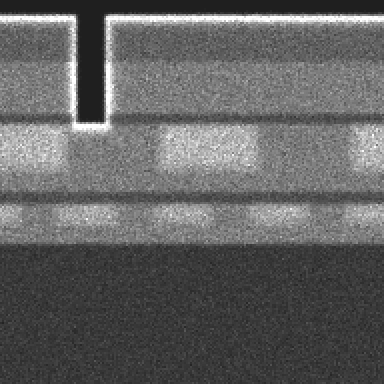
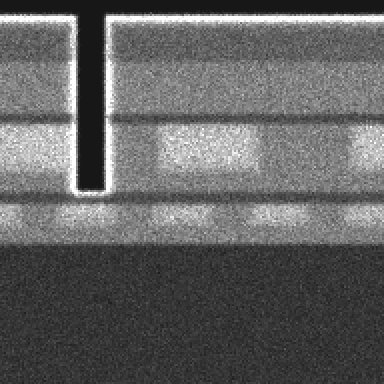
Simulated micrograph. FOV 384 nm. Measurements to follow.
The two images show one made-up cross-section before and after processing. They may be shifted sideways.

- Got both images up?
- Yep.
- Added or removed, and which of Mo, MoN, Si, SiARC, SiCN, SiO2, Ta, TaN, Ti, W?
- removed, SiO2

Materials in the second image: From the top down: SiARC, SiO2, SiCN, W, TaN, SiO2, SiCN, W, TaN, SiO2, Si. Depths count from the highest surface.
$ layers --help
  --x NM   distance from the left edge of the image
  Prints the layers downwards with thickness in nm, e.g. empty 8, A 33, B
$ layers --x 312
SiARC 46, SiO2 52, SiCN 10, SiO2 68, SiCN 12, SiO2 40, Si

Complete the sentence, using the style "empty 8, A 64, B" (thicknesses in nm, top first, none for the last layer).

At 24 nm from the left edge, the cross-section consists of SiARC 46, SiO2 52, SiCN 10, W 40, TaN 8, SiO2 20, SiCN 12, SiO2 40, Si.